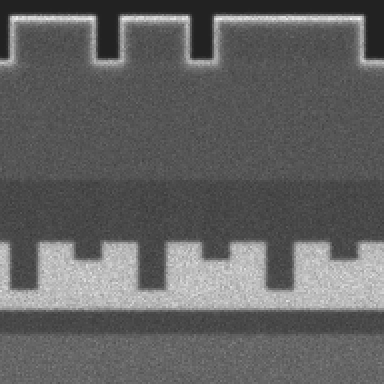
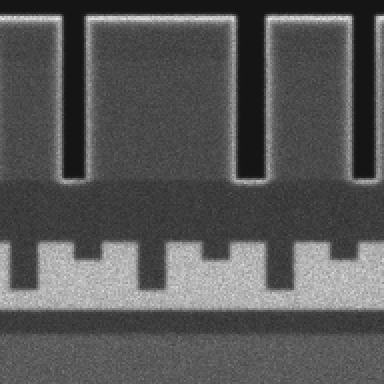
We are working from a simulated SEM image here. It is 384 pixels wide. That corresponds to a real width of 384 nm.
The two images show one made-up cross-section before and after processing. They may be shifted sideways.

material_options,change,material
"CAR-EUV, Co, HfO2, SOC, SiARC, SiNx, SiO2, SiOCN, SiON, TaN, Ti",removed,SOC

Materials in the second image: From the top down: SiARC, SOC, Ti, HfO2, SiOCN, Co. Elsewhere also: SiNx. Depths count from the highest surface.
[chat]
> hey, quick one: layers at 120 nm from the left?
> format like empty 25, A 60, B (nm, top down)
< SiARC 44, SOC 120, SiNx 62, HfO2 68, SiOCN 24, Co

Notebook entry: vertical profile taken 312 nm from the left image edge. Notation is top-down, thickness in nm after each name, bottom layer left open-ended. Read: SiARC 44, SOC 120, SiNx 62, HfO2 68, SiOCN 24, Co